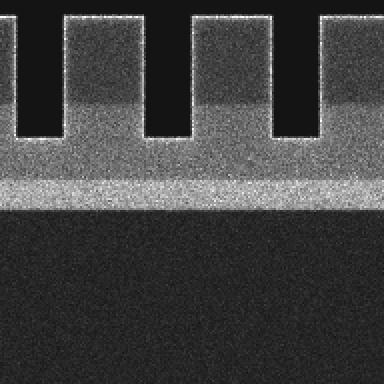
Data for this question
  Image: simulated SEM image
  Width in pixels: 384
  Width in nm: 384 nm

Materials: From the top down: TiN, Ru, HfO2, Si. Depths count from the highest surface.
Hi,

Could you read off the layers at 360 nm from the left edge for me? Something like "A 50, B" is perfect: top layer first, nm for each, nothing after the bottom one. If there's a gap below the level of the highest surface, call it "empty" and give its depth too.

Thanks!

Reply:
TiN 88, Ru 76, HfO2 30, Si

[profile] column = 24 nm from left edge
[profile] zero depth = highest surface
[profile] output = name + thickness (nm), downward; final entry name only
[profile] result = empty 122, Ru 42, HfO2 30, Si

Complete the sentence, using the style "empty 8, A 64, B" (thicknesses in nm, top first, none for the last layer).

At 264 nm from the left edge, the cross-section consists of TiN 88, Ru 76, HfO2 30, Si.